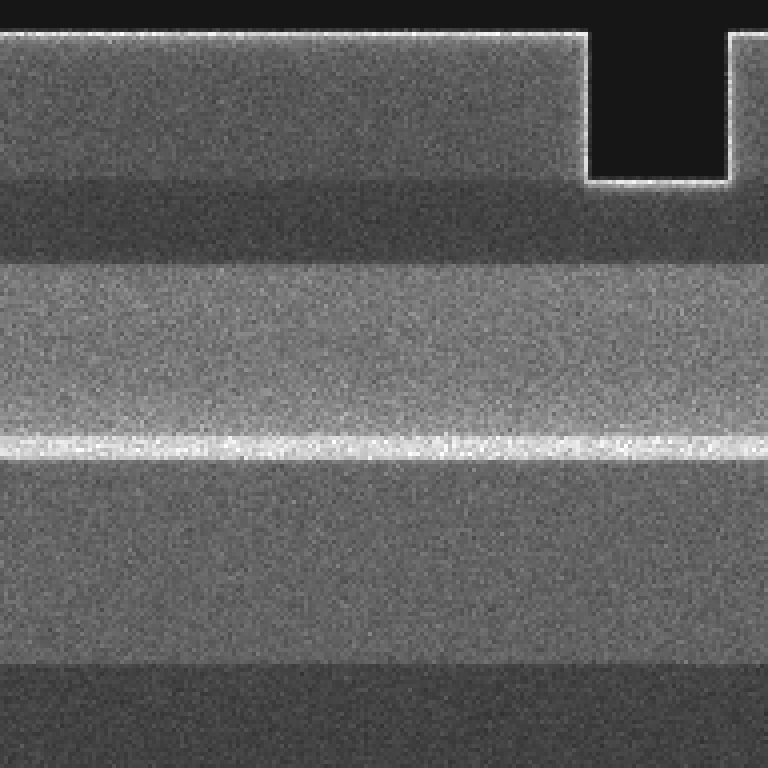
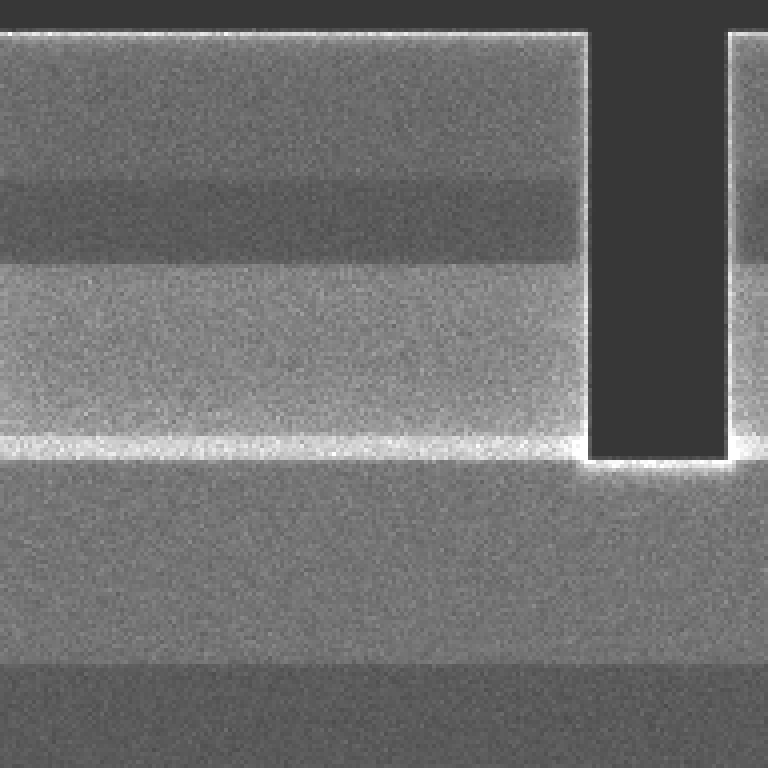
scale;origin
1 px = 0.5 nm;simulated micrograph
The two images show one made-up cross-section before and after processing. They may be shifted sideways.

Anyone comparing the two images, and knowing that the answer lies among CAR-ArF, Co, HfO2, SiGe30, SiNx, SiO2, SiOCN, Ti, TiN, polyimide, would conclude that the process removed Co and HfO2 and SiNx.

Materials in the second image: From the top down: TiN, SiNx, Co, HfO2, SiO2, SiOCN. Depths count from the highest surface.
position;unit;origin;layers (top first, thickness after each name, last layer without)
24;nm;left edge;TiN 74, SiNx 42, Co 86, HfO2 12, SiO2 102, SiOCN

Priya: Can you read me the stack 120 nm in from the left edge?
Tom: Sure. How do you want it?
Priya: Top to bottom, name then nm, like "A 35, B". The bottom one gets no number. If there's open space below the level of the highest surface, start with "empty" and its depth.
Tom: TiN 74, SiNx 42, Co 86, HfO2 12, SiO2 102, SiOCN